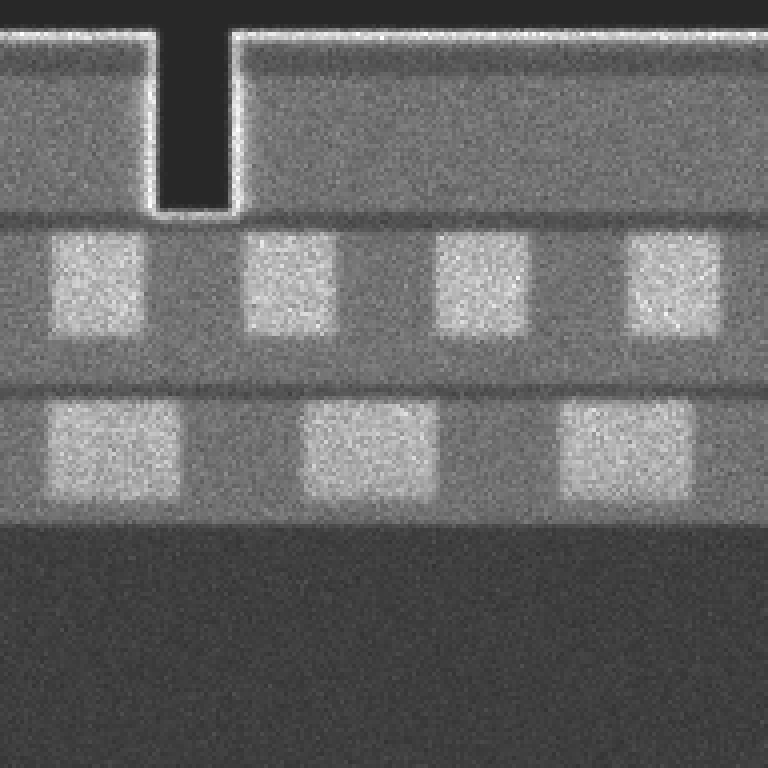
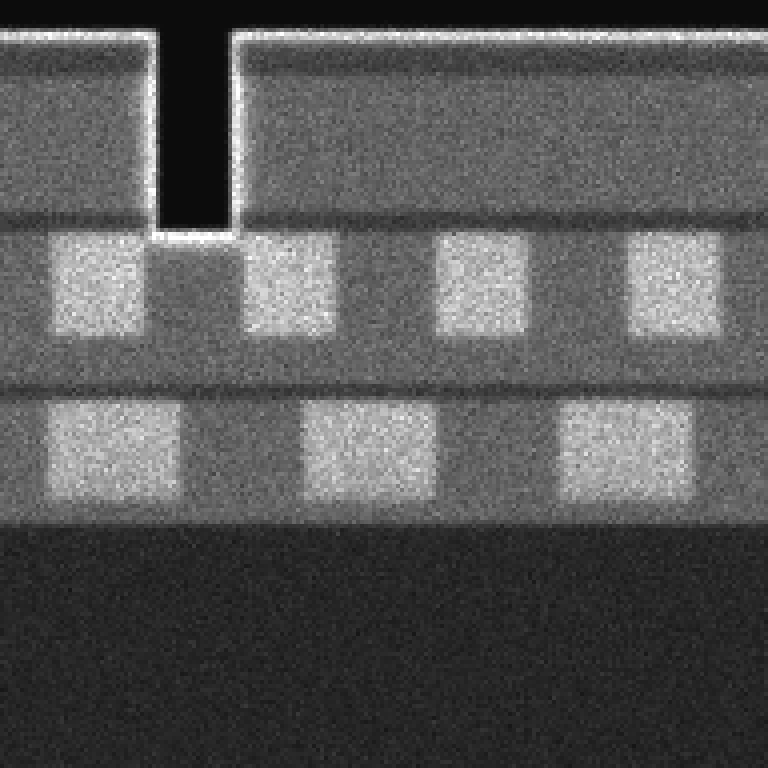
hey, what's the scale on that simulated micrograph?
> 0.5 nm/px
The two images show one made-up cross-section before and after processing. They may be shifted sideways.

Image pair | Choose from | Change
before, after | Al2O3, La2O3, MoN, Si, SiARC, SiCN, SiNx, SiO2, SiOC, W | SiCN (removed)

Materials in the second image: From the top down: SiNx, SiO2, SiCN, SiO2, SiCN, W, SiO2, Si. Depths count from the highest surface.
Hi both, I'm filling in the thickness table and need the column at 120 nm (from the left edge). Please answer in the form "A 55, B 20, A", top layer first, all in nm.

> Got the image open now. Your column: SiNx 22, SiO2 68, SiCN 10, SiO2 76, SiCN 8, SiO2 62, Si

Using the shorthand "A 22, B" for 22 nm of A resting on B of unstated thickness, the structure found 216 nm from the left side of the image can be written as SiNx 22, SiO2 68, SiCN 10, SiO2 76, SiCN 8, W 50, SiO2 12, Si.